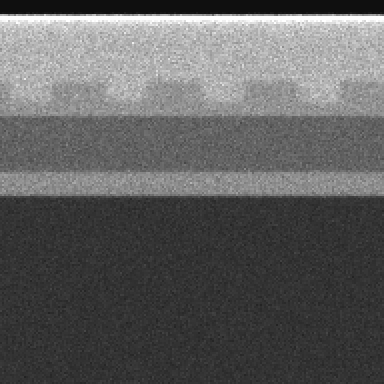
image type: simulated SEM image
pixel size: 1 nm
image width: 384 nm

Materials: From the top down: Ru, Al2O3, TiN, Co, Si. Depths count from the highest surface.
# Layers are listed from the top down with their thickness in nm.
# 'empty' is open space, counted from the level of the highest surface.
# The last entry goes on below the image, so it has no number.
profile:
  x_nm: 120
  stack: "Ru 86, Al2O3 14, TiN 56, Co 24, Si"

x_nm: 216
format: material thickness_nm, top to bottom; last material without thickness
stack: Ru 86, Al2O3 14, TiN 56, Co 24, Si